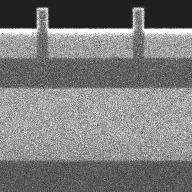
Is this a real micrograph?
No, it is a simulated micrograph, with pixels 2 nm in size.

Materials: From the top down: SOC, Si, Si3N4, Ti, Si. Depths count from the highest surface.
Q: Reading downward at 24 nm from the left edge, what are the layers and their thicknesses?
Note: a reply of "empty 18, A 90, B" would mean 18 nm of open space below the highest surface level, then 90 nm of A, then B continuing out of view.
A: empty 42, SOC 58, Si 60, Si3N4 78, Ti 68, Si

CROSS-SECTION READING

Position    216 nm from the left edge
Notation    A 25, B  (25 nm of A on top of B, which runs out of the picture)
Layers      empty 42, SOC 58, Si 60, Si3N4 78, Ti 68, Si